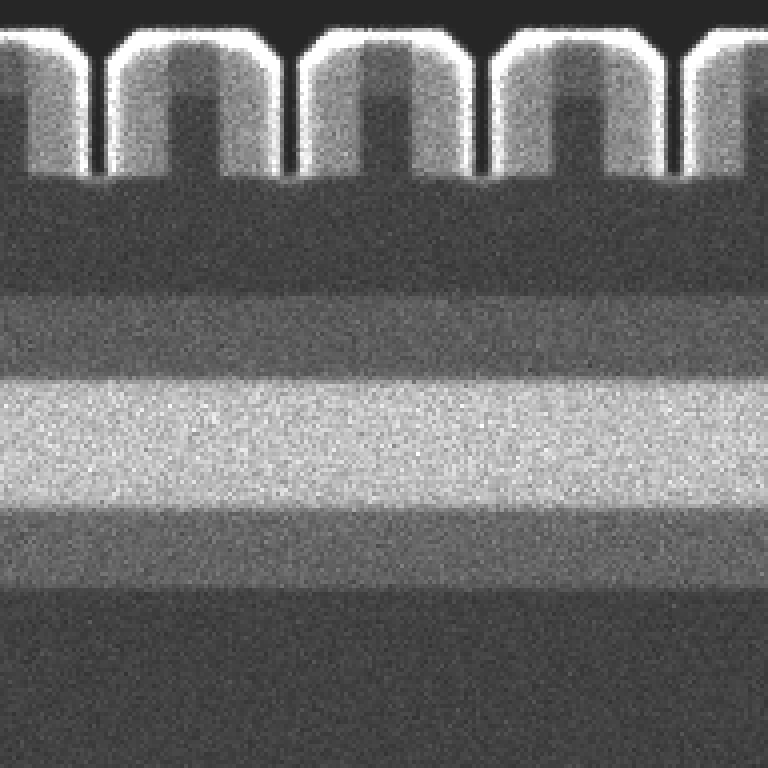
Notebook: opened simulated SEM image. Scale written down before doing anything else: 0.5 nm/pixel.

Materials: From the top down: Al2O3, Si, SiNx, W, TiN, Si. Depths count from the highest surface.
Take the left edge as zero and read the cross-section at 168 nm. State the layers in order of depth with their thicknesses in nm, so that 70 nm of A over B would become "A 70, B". Al2O3 72, Si 60, SiNx 42, W 64, TiN 40, Si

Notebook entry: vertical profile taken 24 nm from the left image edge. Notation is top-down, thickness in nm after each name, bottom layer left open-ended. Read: Al2O3 72, Si 60, SiNx 42, W 64, TiN 40, Si